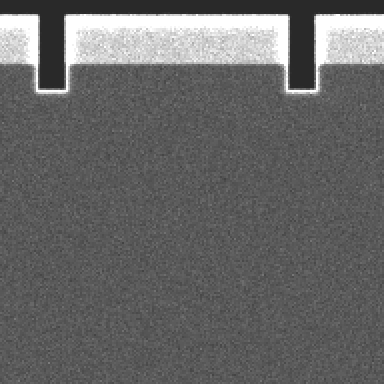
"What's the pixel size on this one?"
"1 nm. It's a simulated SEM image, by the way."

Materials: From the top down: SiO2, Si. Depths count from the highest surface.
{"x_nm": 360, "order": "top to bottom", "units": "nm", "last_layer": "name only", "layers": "SiO2 48, Si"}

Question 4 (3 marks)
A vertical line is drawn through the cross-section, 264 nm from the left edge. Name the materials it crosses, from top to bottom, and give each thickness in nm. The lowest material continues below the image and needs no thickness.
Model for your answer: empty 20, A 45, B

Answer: SiO2 48, Si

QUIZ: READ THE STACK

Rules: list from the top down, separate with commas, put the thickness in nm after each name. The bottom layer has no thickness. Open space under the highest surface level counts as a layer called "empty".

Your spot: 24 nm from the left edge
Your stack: SiO2 48, Si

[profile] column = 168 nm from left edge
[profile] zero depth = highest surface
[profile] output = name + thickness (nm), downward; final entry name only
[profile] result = SiO2 48, Si